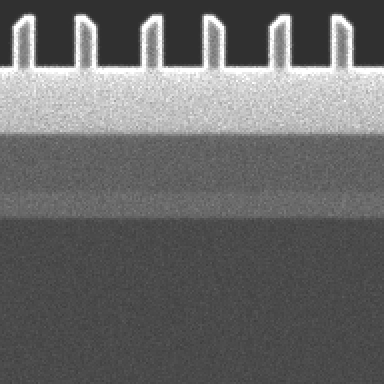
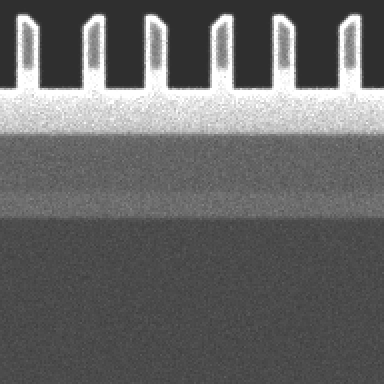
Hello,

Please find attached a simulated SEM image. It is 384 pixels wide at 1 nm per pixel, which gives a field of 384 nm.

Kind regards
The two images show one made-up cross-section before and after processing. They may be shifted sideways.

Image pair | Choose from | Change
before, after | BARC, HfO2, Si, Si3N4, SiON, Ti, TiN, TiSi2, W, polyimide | W (removed)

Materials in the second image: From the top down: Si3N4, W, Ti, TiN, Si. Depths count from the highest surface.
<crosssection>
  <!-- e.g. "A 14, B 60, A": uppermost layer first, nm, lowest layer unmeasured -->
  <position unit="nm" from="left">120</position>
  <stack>empty 74, W 44, Ti 58, TiN 26, Si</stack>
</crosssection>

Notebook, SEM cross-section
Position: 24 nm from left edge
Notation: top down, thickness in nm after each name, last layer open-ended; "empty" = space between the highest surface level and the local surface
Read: Si3N4 52, W 66, Ti 58, TiN 26, Si